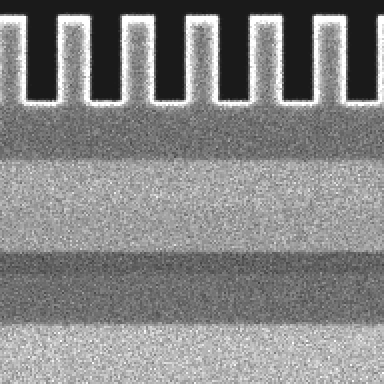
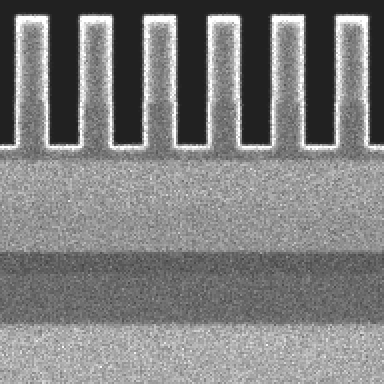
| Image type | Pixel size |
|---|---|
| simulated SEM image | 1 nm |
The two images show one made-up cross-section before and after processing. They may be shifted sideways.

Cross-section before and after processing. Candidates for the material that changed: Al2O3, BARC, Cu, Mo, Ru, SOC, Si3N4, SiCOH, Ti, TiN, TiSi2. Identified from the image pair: TiN (removed).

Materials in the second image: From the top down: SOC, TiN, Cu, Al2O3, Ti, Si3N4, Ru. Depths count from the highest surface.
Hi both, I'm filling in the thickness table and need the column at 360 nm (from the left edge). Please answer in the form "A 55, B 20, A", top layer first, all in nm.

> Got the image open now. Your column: SOC 86, TiN 58, Cu 48, Al2O3 44, Ti 22, Si3N4 50, Ru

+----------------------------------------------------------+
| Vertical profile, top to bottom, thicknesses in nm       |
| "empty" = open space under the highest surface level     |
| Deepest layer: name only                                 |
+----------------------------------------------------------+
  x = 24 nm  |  SOC 86, TiN 58, Cu 48, Al2O3 44, Ti 22, Si3N4 50, Ru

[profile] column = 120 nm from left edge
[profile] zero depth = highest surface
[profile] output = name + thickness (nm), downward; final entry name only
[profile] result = empty 130, TiN 14, Cu 48, Al2O3 44, Ti 22, Si3N4 50, Ru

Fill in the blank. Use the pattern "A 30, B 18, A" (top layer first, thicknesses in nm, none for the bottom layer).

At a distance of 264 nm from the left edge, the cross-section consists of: empty 130, TiN 14, Cu 48, Al2O3 44, Ti 22, Si3N4 50, Ru